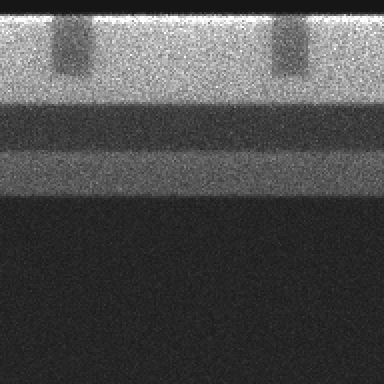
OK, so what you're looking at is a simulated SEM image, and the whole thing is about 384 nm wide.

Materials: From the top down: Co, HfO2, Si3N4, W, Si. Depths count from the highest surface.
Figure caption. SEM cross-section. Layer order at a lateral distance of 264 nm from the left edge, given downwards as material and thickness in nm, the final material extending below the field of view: HfO2 88, Si3N4 48, W 44, Si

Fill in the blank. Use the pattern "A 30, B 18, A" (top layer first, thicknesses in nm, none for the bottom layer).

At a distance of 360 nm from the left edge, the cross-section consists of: HfO2 88, Si3N4 48, W 44, Si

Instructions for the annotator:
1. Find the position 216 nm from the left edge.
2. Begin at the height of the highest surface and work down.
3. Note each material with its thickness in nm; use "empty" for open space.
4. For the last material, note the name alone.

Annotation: HfO2 88, Si3N4 48, W 44, Si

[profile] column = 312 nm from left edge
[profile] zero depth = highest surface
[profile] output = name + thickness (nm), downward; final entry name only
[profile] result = HfO2 88, Si3N4 48, W 44, Si